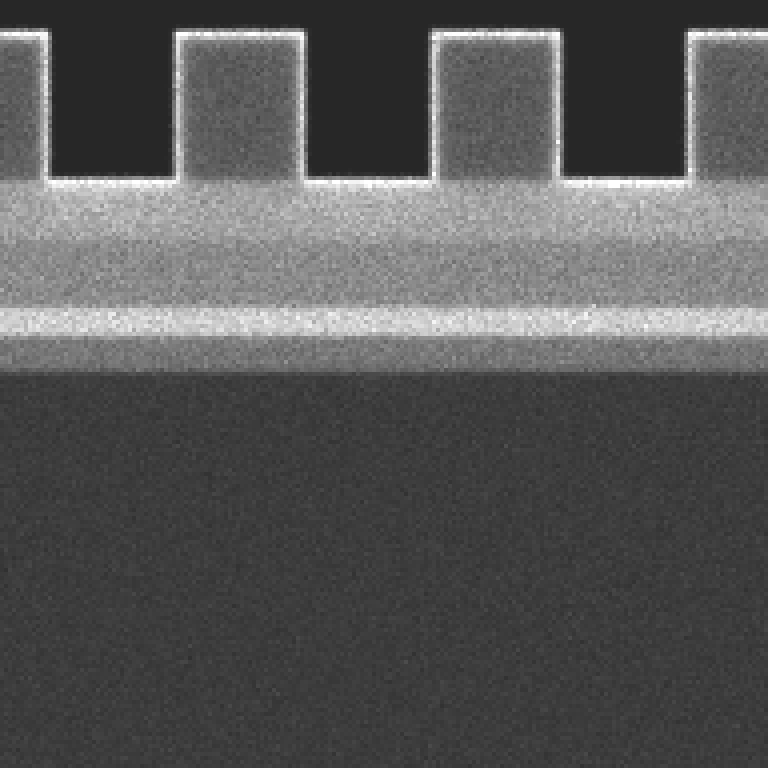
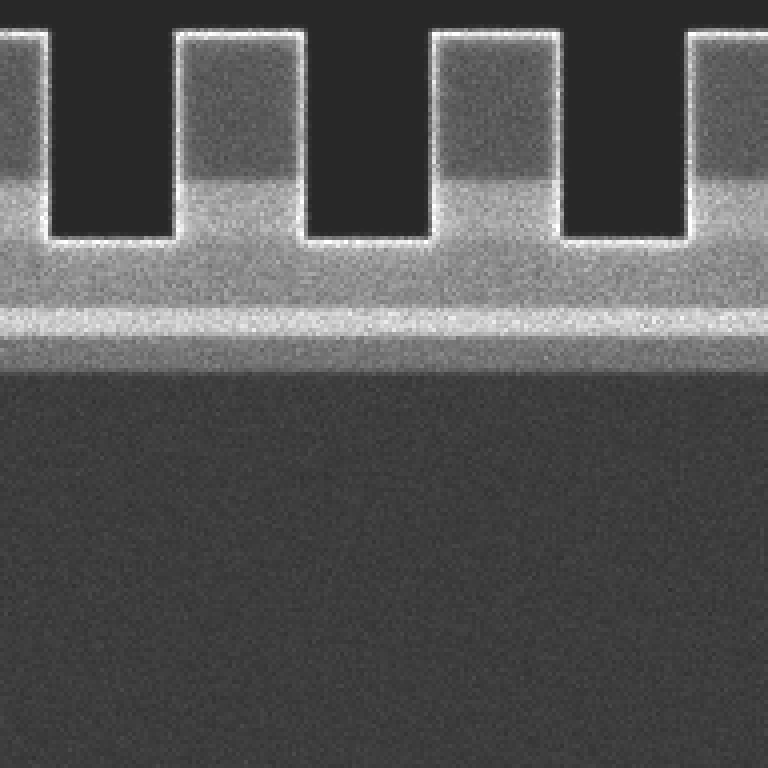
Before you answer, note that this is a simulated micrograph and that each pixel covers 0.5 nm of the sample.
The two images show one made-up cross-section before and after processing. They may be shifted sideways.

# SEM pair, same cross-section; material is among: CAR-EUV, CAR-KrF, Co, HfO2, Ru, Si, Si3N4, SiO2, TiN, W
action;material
removed;W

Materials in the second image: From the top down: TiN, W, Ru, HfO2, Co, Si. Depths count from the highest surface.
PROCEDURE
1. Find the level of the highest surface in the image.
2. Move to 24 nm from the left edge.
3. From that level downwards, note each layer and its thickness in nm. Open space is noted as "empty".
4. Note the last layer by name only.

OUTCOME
empty 104, Ru 34, HfO2 14, Co 18, Si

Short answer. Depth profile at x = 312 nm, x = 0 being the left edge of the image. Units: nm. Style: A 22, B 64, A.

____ empty 104, Ru 34, HfO2 14, Co 18, Si